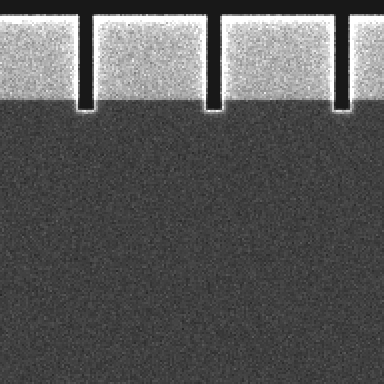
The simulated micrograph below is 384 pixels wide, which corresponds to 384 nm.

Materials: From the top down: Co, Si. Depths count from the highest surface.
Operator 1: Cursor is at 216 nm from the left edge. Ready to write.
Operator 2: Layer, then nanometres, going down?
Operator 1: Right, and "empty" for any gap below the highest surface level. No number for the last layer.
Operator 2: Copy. empty 94, Si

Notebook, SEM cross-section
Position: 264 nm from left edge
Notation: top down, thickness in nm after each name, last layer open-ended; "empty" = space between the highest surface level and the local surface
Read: Co 84, Si